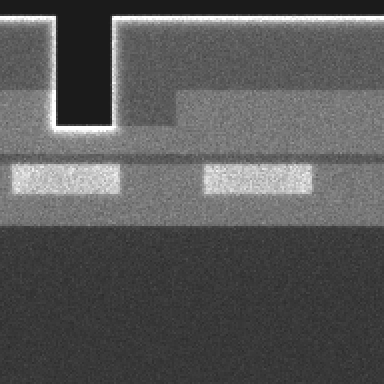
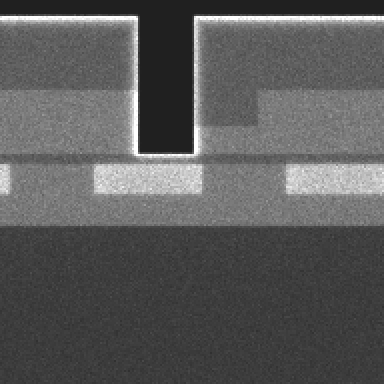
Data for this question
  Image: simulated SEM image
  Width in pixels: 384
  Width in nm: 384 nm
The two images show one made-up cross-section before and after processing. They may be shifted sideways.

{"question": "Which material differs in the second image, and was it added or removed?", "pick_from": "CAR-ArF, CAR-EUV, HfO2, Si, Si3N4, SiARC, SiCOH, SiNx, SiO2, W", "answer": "SiO2, removed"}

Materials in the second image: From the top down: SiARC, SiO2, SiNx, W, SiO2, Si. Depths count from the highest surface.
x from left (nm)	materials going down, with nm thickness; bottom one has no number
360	SiARC 74, SiO2 64, SiNx 10, W 30, SiO2 32, Si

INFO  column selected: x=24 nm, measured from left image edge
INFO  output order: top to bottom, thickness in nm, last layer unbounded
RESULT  SiARC 74, SiO2 64, SiNx 10, SiO2 62, Si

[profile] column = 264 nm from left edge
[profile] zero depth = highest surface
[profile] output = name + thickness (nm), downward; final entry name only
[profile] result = SiARC 74, SiO2 64, SiNx 10, SiO2 62, Si